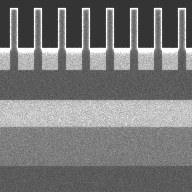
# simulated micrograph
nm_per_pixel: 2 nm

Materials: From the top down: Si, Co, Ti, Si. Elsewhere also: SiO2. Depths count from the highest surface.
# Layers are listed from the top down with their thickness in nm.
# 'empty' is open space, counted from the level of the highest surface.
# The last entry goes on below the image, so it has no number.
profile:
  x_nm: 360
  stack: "Si 184, Co 54, Ti 78, Si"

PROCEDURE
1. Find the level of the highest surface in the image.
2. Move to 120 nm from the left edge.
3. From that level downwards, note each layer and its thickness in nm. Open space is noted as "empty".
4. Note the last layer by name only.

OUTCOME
Si 184, Co 54, Ti 78, Si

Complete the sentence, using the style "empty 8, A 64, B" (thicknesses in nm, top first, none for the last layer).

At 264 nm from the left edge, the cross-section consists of Si 184, Co 54, Ti 78, Si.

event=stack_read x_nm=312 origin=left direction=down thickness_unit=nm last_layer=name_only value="Si 184, Co 54, Ti 78, Si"